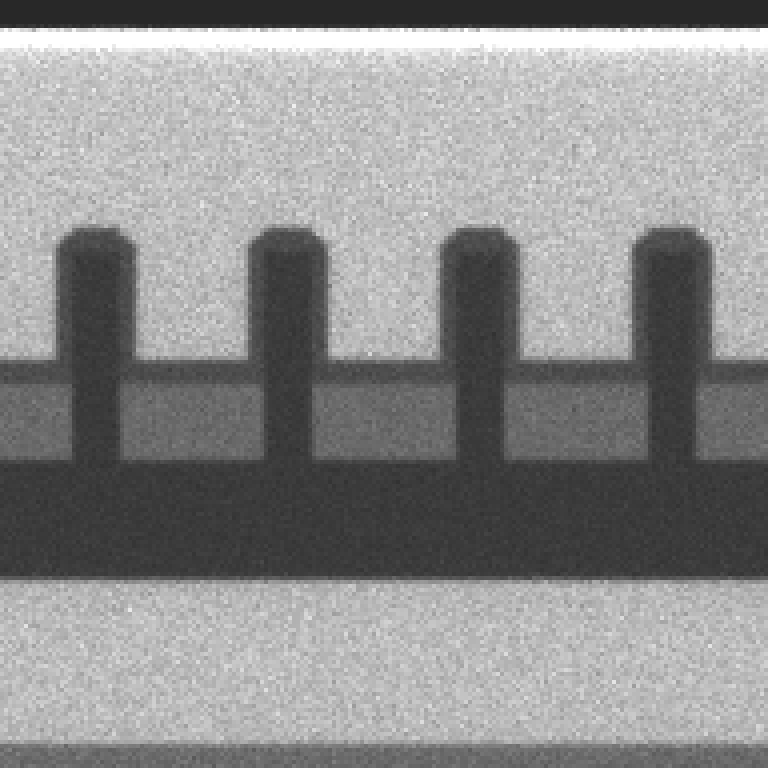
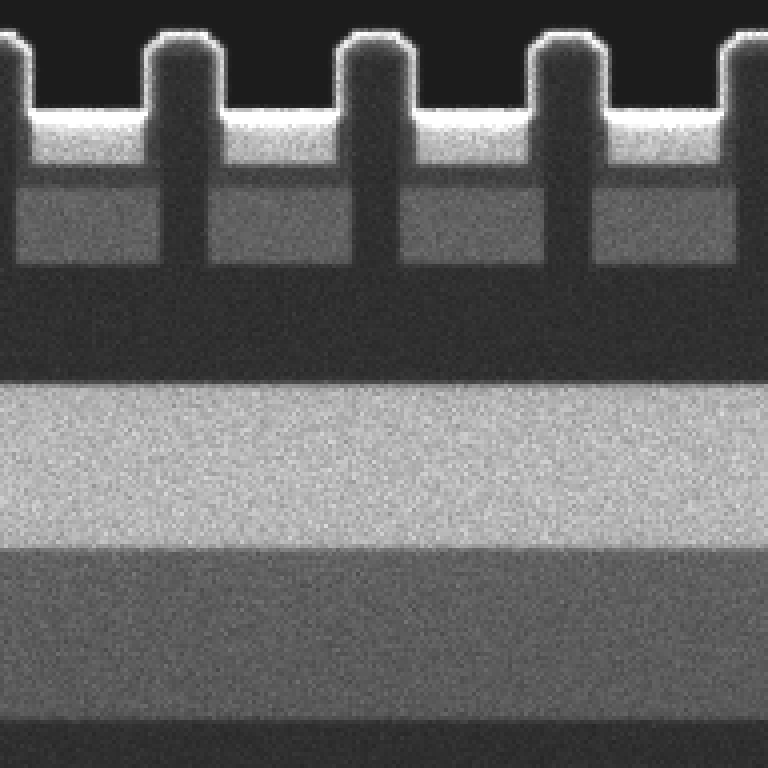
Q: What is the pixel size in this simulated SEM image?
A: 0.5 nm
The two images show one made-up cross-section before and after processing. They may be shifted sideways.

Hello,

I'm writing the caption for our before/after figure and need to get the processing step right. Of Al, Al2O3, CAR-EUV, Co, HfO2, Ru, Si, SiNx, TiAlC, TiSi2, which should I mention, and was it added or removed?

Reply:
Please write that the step removed HfO2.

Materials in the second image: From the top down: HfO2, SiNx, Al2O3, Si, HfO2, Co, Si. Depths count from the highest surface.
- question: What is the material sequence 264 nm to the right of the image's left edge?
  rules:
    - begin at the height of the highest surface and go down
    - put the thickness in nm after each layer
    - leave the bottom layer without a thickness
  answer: empty 8, SiNx 70, Al2O3 38, Si 60, HfO2 82, Co 86, Si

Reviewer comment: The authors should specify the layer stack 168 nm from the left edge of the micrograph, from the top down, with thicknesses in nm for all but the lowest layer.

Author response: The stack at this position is empty 8, SiNx 70, Al2O3 38, Si 60, HfO2 82, Co 86, Si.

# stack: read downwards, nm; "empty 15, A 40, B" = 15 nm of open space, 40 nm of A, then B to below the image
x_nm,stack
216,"empty 40, HfO2 26, SiNx 12, Al2O3 38, Si 60, HfO2 82, Co 86, Si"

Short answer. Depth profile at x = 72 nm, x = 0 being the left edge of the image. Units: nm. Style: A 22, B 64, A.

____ empty 8, SiNx 70, Al2O3 38, Si 60, HfO2 82, Co 86, Si